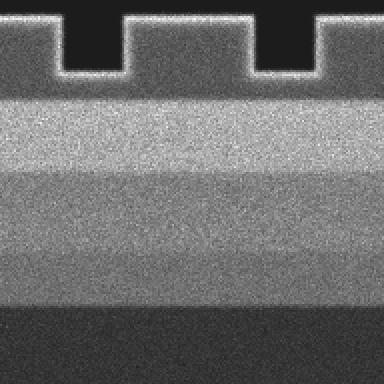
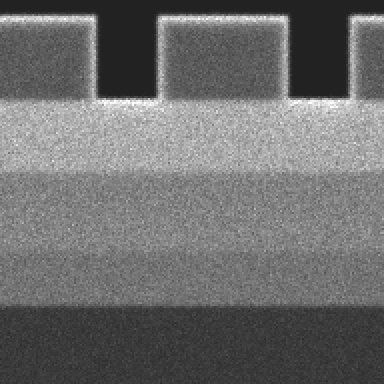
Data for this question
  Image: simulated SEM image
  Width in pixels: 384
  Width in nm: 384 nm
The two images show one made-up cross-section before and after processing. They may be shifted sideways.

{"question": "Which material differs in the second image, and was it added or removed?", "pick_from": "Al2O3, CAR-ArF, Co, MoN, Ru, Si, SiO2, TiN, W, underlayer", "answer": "underlayer, removed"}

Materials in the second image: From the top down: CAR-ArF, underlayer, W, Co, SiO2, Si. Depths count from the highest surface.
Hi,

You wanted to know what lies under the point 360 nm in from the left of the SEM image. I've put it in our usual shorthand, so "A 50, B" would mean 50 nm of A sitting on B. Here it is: CAR-ArF 56, underlayer 28, W 72, Co 80, SiO2 54, Si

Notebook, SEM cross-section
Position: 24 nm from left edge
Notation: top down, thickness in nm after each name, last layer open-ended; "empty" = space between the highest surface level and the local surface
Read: CAR-ArF 56, underlayer 28, W 72, Co 80, SiO2 54, Si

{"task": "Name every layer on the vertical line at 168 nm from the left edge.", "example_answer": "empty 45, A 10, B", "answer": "CAR-ArF 56, underlayer 28, W 72, Co 80, SiO2 54, Si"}